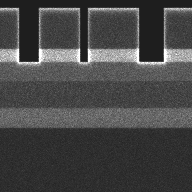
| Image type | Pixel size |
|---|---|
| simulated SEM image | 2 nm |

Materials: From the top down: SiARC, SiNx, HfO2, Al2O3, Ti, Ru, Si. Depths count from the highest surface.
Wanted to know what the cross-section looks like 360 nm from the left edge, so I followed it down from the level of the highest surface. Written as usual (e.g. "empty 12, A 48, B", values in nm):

SiARC 14, SiNx 68, HfO2 26, Al2O3 38, Ti 54, Ru 40, Si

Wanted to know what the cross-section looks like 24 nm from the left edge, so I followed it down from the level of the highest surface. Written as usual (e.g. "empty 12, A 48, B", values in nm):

SiARC 14, SiNx 68, HfO2 26, Al2O3 38, Ti 54, Ru 40, Si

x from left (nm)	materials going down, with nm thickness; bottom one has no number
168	empty 108, Al2O3 38, Ti 54, Ru 40, Si